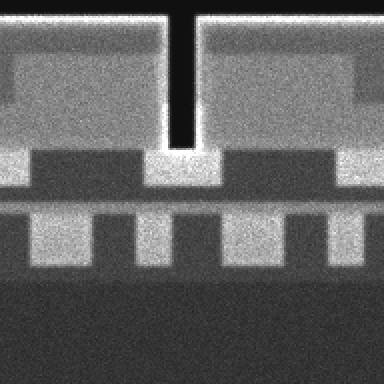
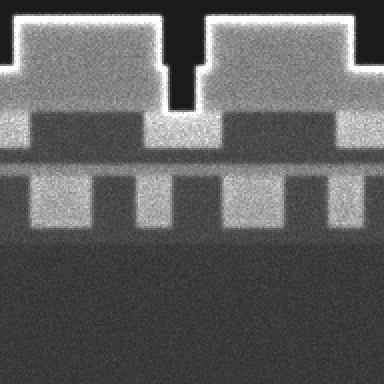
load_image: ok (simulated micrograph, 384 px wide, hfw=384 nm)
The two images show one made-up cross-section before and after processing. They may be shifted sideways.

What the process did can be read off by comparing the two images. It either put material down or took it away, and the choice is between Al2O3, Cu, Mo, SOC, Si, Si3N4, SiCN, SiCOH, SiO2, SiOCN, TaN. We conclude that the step removed SOC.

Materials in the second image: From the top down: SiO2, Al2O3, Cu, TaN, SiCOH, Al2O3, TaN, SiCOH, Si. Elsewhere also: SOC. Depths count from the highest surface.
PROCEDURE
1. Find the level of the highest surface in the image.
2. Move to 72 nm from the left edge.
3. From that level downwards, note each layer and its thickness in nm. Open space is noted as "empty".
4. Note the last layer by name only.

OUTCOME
SiO2 84, Al2O3 12, SiCOH 52, Al2O3 12, Cu 44, TaN 8, SiCOH 16, Si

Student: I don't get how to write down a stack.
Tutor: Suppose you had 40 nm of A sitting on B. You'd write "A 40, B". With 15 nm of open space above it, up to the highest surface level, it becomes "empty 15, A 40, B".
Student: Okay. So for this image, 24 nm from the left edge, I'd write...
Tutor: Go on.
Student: SiO2 84, Al2O3 12, TaN 36, SiCOH 16, Al2O3 12, SiCOH 68, Si